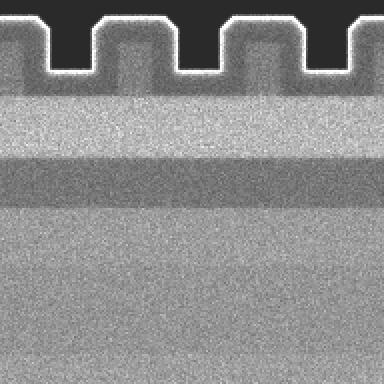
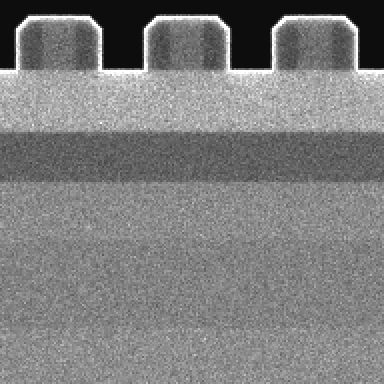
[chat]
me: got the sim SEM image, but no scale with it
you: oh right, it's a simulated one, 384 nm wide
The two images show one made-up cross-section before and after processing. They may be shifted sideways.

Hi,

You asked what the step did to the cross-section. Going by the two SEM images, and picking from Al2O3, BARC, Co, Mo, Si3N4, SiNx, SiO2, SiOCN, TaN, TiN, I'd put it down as SiOCN, removed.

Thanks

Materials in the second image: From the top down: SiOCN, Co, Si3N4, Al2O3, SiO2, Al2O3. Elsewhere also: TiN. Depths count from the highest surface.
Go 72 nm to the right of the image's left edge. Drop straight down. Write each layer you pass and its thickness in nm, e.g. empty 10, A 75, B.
TiN 54, Co 62, Si3N4 50, Al2O3 58, SiO2 88, Al2O3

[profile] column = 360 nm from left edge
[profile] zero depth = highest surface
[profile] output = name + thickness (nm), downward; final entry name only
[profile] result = empty 54, Co 62, Si3N4 50, Al2O3 58, SiO2 88, Al2O3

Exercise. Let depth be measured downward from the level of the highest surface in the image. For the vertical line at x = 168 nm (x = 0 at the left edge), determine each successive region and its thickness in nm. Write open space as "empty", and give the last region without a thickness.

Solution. SiOCN 54, Co 62, Si3N4 50, Al2O3 58, SiO2 88, Al2O3